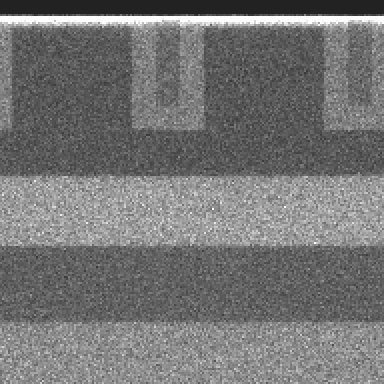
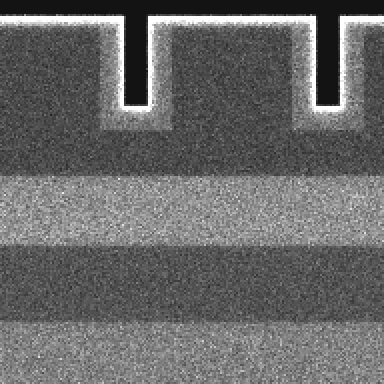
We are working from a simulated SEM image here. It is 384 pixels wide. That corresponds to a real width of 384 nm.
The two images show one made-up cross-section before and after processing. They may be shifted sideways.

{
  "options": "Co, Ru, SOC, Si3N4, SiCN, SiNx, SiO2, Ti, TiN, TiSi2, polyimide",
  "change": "removed",
  "material": "SOC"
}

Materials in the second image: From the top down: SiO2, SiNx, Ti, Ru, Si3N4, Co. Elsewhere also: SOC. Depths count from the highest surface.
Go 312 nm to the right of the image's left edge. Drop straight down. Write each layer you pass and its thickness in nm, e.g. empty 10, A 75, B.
SiO2 114, Ti 46, Ru 70, Si3N4 76, Co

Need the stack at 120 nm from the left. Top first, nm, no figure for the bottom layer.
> SiO2 114, Ti 46, Ru 70, Si3N4 76, Co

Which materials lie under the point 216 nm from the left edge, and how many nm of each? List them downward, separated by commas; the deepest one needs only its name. SiO2 10, SiNx 78, Ti 72, Ru 70, Si3N4 76, Co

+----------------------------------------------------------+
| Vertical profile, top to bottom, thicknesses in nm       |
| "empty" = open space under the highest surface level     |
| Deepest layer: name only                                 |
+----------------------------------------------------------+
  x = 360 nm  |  SiO2 114, Ti 46, Ru 70, Si3N4 76, Co